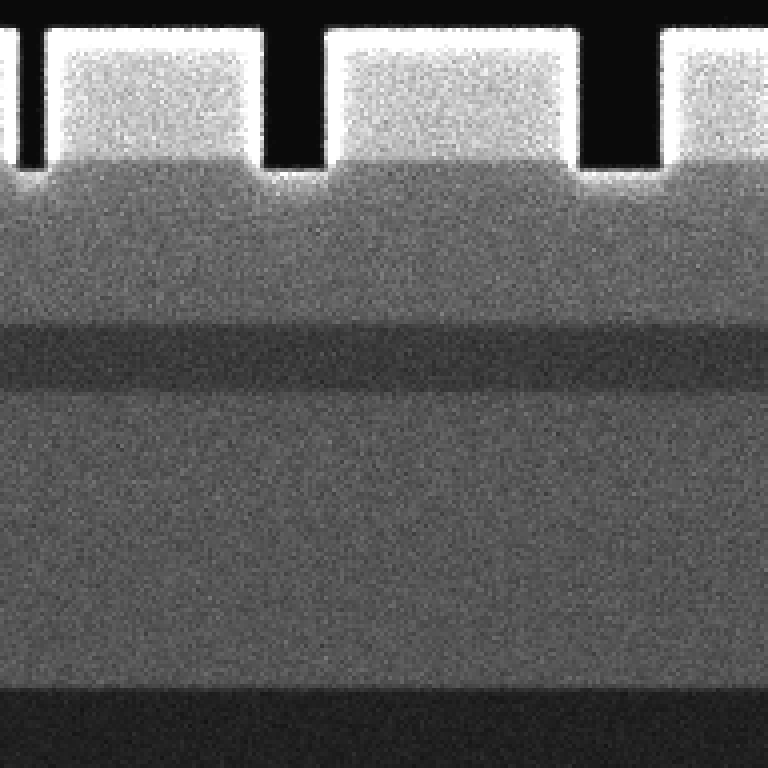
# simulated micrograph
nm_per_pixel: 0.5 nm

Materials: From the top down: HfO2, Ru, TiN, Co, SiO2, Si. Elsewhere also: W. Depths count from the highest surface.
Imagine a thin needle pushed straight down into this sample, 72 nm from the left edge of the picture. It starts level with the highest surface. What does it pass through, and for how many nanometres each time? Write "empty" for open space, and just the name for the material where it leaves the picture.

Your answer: HfO2 64, Ru 82, TiN 34, Co 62, SiO2 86, Si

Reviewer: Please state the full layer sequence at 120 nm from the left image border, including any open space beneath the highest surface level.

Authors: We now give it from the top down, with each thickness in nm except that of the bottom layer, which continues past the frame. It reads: HfO2 64, Ru 82, TiN 34, Co 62, SiO2 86, Si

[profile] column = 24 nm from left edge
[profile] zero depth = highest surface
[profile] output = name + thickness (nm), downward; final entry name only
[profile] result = HfO2 64, Ru 82, TiN 34, Co 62, SiO2 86, Si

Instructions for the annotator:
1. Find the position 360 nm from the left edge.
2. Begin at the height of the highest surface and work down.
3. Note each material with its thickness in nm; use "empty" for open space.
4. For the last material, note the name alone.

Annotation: HfO2 64, Ru 82, TiN 34, Co 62, SiO2 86, Si